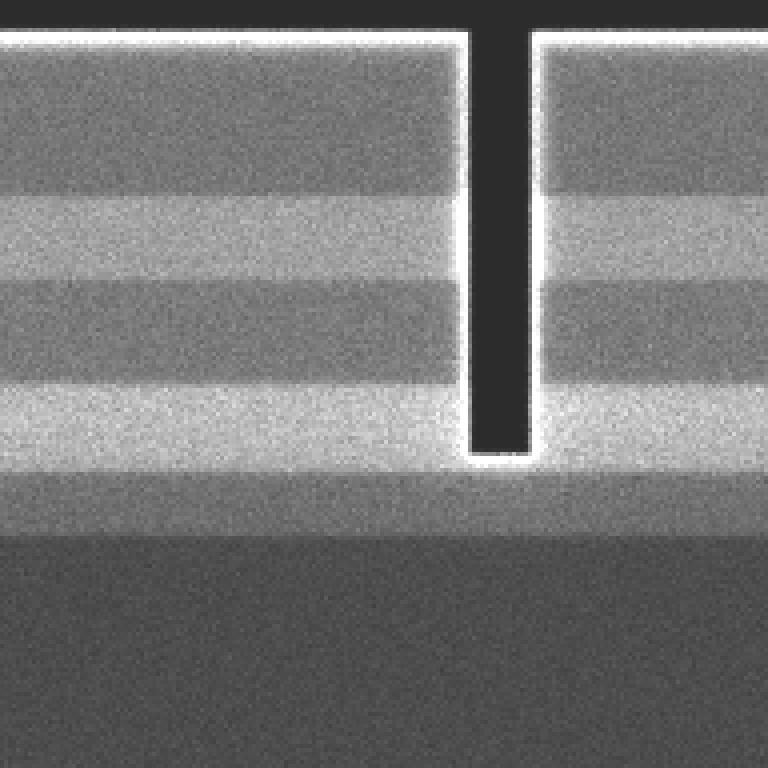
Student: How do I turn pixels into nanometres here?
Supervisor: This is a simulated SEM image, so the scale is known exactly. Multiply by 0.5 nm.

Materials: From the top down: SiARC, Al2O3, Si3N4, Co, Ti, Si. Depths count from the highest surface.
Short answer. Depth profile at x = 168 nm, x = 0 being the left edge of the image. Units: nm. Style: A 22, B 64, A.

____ SiARC 82, Al2O3 42, Si3N4 52, Co 44, Ti 32, Si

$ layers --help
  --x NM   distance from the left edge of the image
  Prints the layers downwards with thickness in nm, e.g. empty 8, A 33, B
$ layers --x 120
SiARC 82, Al2O3 42, Si3N4 52, Co 44, Ti 32, Si